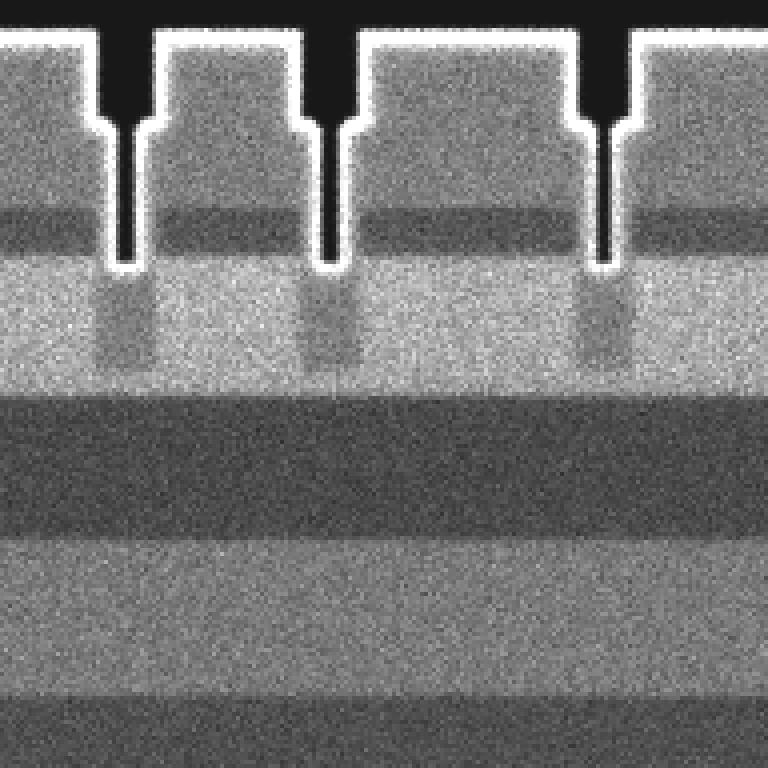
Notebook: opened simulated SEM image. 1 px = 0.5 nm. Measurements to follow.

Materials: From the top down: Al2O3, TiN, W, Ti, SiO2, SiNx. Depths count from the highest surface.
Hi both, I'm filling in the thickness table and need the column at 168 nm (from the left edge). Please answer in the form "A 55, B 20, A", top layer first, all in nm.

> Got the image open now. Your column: empty 116, Al2O3 54, W 12, Ti 72, SiO2 78, SiNx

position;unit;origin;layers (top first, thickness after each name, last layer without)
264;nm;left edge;Al2O3 88, TiN 24, W 70, Ti 72, SiO2 78, SiNx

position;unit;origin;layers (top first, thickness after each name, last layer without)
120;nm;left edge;Al2O3 88, TiN 24, W 70, Ti 72, SiO2 78, SiNx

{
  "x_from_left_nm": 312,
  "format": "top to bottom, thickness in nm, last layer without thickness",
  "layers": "empty 44, Al2O3 126, W 12, Ti 72, SiO2 78, SiNx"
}